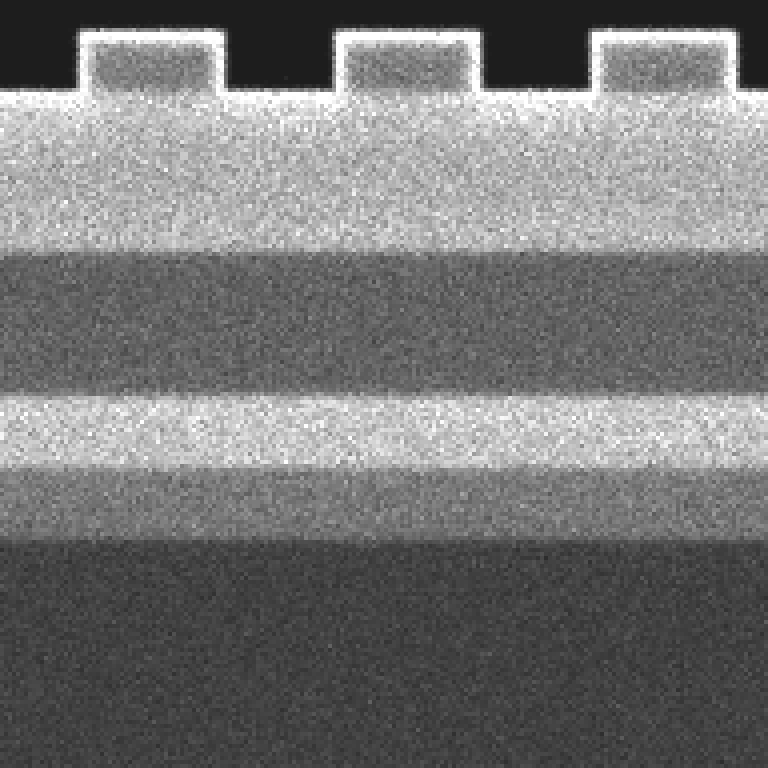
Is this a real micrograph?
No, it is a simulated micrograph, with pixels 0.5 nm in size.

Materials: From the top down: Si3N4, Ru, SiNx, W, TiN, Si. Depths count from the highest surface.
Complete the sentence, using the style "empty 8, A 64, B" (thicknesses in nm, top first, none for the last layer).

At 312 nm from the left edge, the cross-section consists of Si3N4 30, Ru 80, SiNx 72, W 36, TiN 36, Si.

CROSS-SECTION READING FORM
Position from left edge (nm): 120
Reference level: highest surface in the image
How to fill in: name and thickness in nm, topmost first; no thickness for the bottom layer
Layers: empty 30, Ru 80, SiNx 72, W 36, TiN 36, Si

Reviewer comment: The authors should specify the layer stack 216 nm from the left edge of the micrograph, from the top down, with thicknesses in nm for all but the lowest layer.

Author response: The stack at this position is Si3N4 30, Ru 80, SiNx 72, W 36, TiN 36, Si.